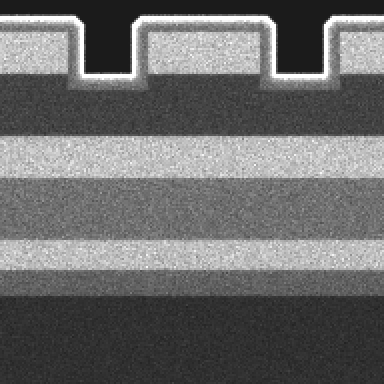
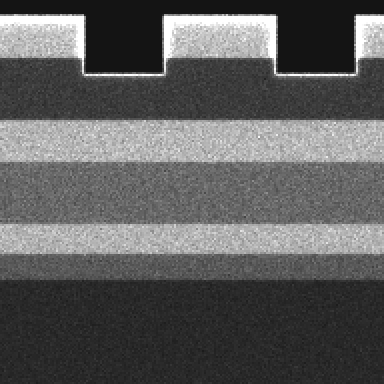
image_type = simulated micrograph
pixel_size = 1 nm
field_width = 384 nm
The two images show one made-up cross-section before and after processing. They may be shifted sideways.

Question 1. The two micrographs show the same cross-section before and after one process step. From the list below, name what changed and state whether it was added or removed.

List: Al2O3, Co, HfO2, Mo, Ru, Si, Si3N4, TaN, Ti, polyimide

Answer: Al2O3, removed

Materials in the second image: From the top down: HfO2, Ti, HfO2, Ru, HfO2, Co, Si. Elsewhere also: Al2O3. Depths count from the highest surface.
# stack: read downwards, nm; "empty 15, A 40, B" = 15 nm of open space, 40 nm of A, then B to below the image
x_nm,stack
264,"HfO2 42, Ti 62, HfO2 42, Ru 62, HfO2 30, Co 26, Si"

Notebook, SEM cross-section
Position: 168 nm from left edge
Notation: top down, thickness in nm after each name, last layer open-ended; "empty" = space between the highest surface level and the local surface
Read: HfO2 42, Ti 62, HfO2 42, Ru 62, HfO2 30, Co 26, Si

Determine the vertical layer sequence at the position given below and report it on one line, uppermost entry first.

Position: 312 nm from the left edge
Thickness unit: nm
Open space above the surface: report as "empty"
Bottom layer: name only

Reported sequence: empty 58, Ti 46, HfO2 42, Ru 62, HfO2 30, Co 26, Si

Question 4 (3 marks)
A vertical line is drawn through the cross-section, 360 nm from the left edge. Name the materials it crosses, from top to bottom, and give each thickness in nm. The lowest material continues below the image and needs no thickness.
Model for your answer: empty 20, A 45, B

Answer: HfO2 42, Ti 62, HfO2 42, Ru 62, HfO2 30, Co 26, Si